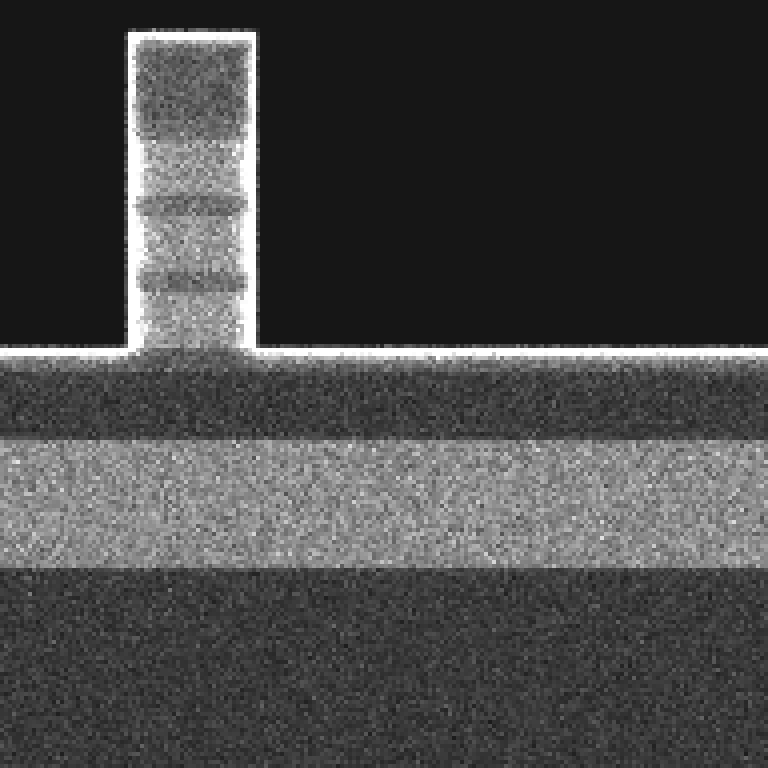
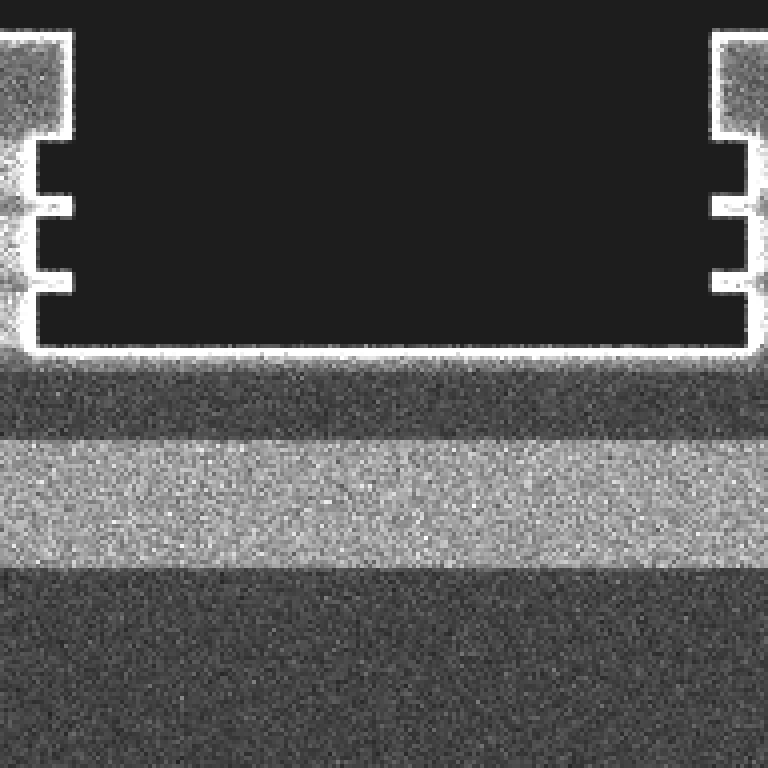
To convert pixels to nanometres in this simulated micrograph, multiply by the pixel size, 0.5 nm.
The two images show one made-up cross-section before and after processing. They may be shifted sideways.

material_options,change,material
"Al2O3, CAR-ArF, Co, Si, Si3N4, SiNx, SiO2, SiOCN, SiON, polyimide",removed,Al2O3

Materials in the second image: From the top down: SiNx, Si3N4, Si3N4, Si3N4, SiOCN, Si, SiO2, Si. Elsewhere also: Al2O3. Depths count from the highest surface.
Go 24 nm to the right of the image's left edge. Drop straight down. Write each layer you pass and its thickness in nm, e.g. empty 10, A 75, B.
SiNx 44, Si3N4 10, empty 28, Si3N4 10, empty 28, Si3N4 10, empty 28, SiOCN 12, Si 34, SiO2 64, Si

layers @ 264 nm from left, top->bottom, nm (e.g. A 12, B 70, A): empty 158, SiOCN 12, Si 34, SiO2 64, Si